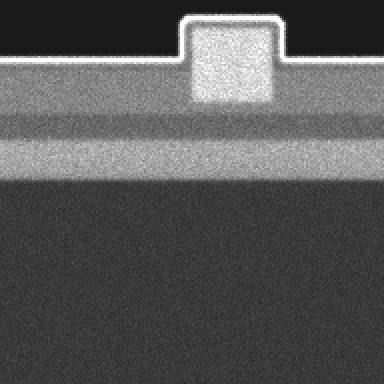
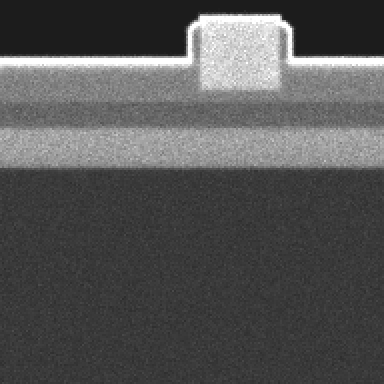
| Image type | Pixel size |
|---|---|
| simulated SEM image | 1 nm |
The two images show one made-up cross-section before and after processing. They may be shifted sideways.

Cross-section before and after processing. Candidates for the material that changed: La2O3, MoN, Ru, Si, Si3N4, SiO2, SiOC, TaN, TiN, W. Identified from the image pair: Si3N4 (removed).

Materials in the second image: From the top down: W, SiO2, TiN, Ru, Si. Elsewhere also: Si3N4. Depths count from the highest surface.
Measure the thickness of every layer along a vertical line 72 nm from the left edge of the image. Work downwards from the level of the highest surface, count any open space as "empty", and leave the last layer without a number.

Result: empty 42, SiO2 44, TiN 26, Ru 40, Si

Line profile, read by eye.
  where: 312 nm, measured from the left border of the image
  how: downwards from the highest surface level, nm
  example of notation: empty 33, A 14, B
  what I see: empty 42, SiO2 44, TiN 26, Ru 40, Si